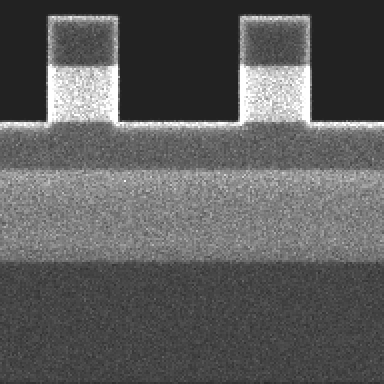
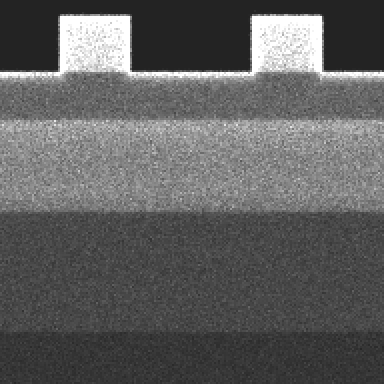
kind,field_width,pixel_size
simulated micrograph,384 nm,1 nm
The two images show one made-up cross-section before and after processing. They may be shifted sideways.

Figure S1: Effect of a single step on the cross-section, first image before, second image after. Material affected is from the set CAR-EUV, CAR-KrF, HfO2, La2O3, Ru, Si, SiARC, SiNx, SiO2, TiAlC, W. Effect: removed SiARC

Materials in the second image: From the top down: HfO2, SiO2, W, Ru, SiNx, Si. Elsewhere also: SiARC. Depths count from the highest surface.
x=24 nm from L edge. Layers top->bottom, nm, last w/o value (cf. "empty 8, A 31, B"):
empty 56, SiO2 48, W 78, Ru 14, SiNx 120, Si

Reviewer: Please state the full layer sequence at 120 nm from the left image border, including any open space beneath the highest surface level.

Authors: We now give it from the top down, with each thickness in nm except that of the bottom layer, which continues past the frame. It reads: HfO2 56, SiO2 48, W 78, Ru 14, SiNx 120, Si